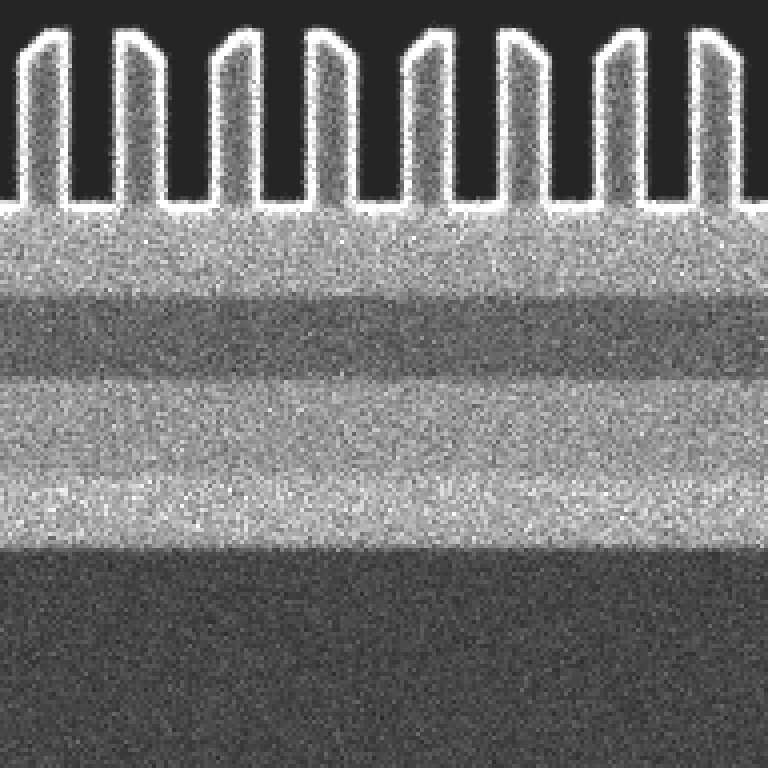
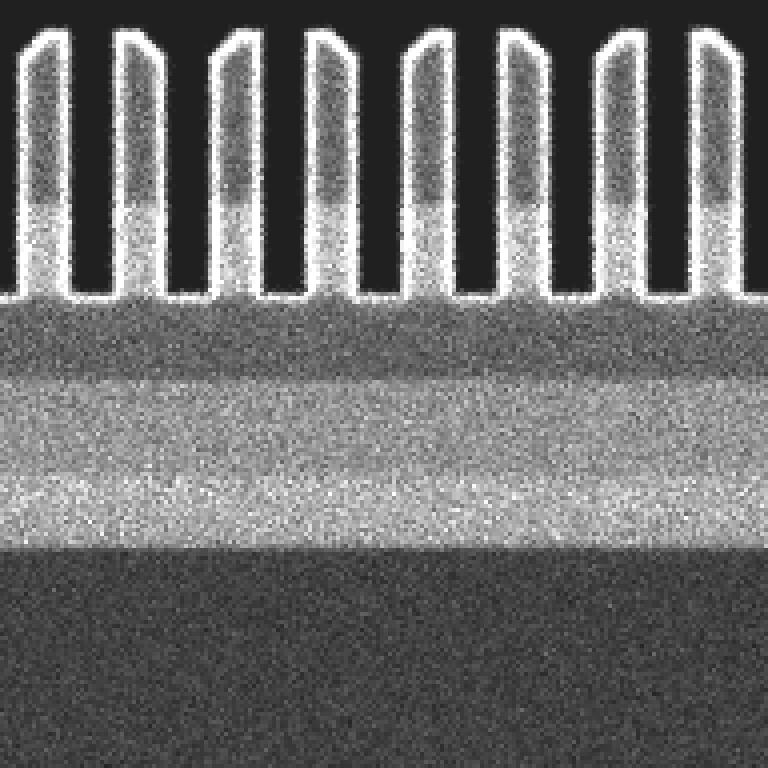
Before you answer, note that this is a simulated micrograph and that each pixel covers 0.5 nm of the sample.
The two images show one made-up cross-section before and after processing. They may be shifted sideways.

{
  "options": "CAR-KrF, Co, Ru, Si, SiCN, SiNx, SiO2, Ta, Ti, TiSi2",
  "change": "removed",
  "material": "Co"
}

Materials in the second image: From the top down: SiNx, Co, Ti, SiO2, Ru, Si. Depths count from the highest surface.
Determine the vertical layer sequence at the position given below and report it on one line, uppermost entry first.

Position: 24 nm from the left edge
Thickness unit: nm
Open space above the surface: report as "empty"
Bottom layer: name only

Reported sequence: SiNx 86, Co 46, Ti 42, SiO2 48, Ru 36, Si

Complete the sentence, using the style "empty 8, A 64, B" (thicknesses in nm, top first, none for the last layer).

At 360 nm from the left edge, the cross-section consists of empty 4, SiNx 82, Co 46, Ti 42, SiO2 48, Ru 36, Si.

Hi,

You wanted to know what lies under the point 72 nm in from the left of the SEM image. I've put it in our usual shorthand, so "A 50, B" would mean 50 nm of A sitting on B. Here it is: empty 4, SiNx 82, Co 46, Ti 42, SiO2 48, Ru 36, Si